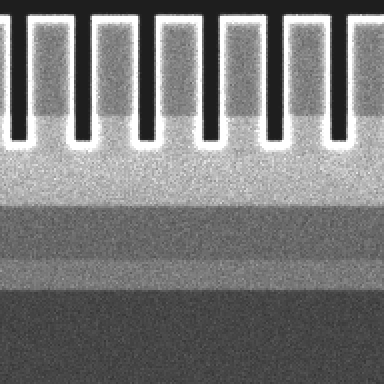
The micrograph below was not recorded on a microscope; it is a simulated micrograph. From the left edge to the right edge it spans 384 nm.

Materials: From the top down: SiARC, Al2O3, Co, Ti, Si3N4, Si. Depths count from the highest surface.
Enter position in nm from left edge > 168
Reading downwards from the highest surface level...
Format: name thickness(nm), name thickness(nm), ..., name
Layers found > SiARC 100, Al2O3 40, Co 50, Ti 54, Si3N4 30, Si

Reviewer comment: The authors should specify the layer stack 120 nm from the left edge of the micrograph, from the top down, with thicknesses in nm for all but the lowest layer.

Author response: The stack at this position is SiARC 100, Al2O3 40, Co 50, Ti 54, Si3N4 30, Si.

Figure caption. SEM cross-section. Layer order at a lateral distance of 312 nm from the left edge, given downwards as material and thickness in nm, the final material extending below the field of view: SiARC 100, Al2O3 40, Co 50, Ti 54, Si3N4 30, Si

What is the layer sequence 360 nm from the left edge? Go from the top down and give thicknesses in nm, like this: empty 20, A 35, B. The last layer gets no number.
SiARC 100, Al2O3 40, Co 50, Ti 54, Si3N4 30, Si